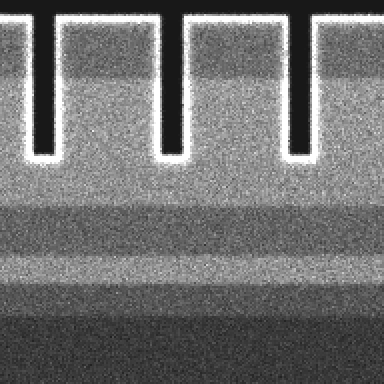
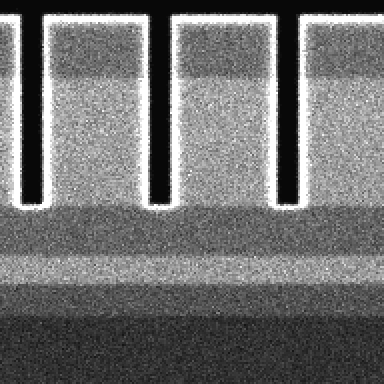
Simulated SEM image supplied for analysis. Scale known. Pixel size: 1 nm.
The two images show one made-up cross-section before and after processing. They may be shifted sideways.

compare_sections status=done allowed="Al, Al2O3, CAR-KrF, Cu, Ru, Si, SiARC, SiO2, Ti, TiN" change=removed material="SiO2"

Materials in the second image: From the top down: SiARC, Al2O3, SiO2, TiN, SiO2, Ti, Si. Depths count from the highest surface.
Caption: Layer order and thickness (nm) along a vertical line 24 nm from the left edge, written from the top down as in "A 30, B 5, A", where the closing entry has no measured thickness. empty 190, TiN 50, SiO2 28, Ti 32, Si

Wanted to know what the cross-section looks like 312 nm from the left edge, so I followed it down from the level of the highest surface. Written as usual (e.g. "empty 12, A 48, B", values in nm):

SiARC 62, Al2O3 78, SiO2 50, TiN 50, SiO2 28, Ti 32, Si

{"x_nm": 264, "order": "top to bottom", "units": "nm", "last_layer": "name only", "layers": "SiARC 62, Al2O3 78, SiO2 50, TiN 50, SiO2 28, Ti 32, Si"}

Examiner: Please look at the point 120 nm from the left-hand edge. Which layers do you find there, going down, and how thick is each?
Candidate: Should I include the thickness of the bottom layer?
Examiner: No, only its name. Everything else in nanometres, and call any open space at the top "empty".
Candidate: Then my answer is SiARC 62, Al2O3 78, SiO2 50, TiN 50, SiO2 28, Ti 32, Si